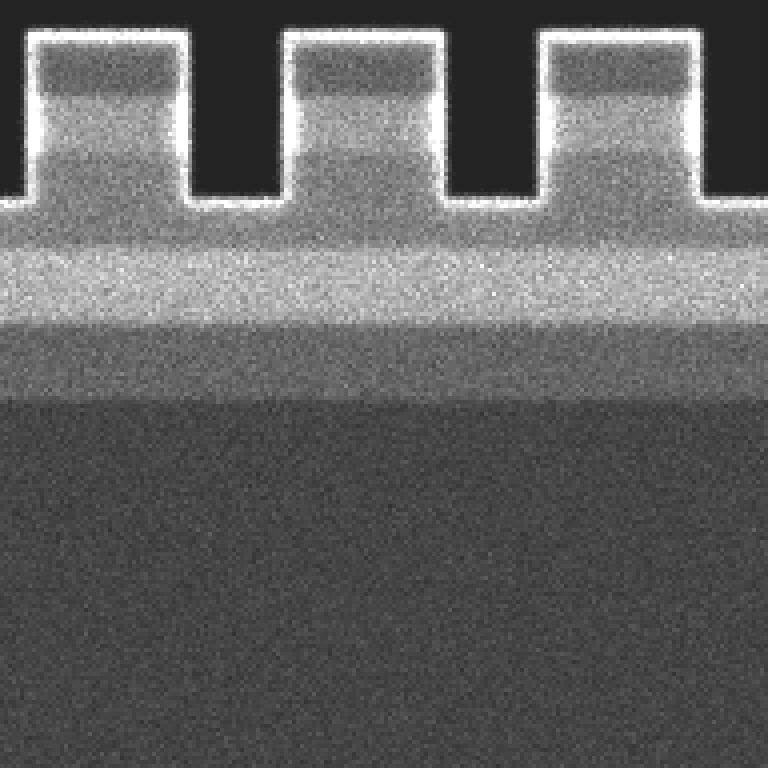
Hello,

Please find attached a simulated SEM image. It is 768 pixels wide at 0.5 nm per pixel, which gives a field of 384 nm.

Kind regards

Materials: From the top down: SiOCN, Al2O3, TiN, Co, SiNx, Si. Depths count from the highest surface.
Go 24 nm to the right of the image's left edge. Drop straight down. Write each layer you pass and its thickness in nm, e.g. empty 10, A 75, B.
SiOCN 32, Al2O3 28, TiN 48, Co 38, SiNx 38, Si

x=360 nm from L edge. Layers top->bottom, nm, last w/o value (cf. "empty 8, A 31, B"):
empty 84, TiN 24, Co 38, SiNx 38, Si